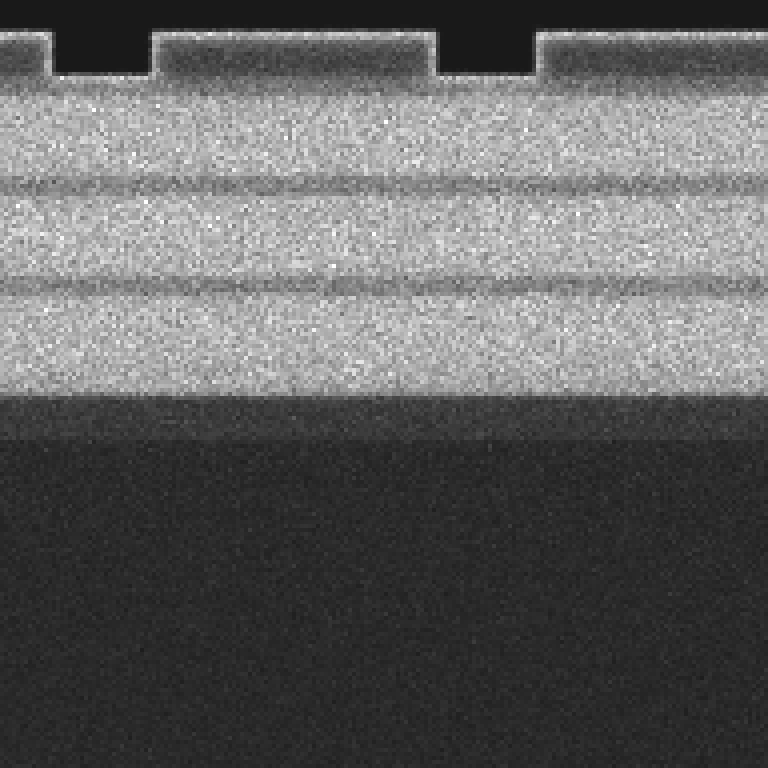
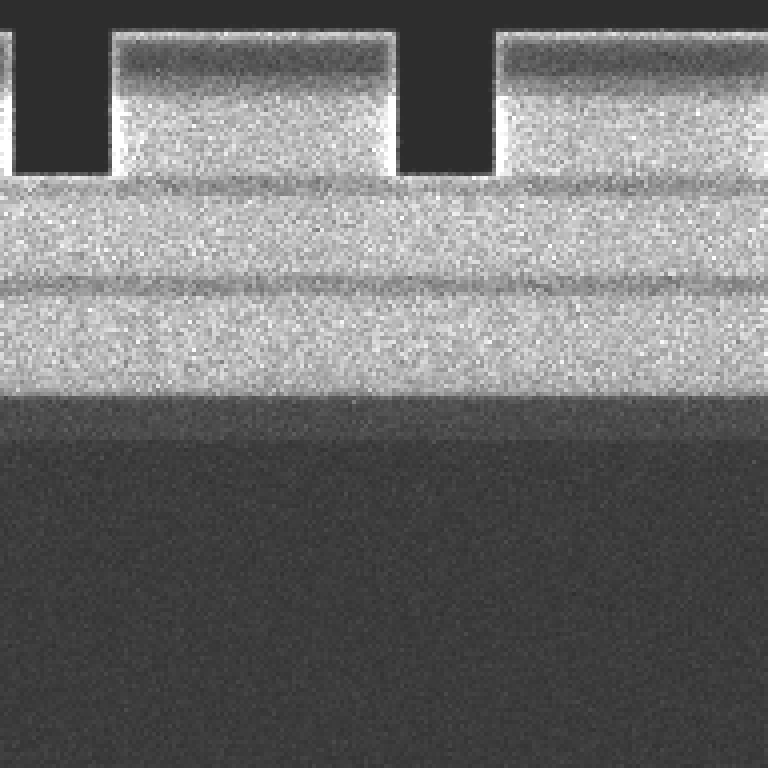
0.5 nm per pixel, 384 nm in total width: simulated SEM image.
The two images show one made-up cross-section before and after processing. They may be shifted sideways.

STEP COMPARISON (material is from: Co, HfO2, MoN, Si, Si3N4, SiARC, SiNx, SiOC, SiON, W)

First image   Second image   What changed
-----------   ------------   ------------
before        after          Co and HfO2, removed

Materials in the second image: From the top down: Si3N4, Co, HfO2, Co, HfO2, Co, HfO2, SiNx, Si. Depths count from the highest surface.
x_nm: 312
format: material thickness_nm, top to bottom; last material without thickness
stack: Si3N4 22, Co 10, HfO2 40, Co 10, HfO2 40, Co 10, HfO2 50, SiNx 22, Si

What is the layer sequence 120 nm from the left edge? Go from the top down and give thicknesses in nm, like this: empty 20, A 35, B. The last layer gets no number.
Si3N4 22, Co 10, HfO2 40, Co 10, HfO2 40, Co 10, HfO2 50, SiNx 22, Si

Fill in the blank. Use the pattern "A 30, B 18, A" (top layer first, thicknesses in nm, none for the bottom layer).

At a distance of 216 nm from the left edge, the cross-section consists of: empty 72, Co 10, HfO2 40, Co 10, HfO2 50, SiNx 22, Si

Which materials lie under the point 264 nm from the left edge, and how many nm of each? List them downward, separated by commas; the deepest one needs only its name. Si3N4 22, Co 10, HfO2 40, Co 10, HfO2 40, Co 10, HfO2 50, SiNx 22, Si